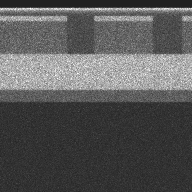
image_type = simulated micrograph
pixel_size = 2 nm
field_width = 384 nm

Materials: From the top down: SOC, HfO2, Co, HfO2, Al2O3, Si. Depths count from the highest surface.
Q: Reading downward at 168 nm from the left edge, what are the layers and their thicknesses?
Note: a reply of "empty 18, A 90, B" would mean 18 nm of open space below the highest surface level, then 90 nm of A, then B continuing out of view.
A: SOC 92, HfO2 72, Al2O3 24, Si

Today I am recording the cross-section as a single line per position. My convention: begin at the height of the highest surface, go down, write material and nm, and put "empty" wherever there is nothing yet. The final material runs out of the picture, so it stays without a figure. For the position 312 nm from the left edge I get SOC 92, HfO2 72, Al2O3 24, Si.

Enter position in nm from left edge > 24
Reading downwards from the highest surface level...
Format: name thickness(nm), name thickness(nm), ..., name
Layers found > SOC 16, HfO2 10, Co 66, HfO2 72, Al2O3 24, Si